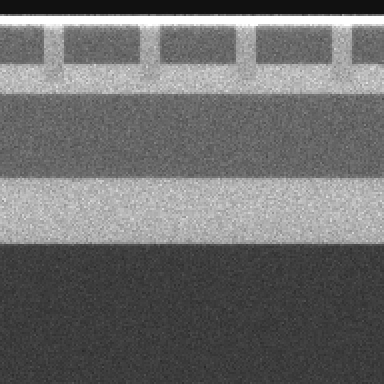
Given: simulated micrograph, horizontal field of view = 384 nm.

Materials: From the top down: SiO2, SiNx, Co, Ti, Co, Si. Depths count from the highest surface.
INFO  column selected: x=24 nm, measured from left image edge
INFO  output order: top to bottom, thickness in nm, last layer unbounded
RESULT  SiO2 8, SiNx 40, Co 30, Ti 84, Co 66, Si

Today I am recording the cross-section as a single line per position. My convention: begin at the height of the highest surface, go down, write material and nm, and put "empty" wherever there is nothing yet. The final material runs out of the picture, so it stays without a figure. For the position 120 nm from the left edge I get SiO2 8, SiNx 40, Co 30, Ti 84, Co 66, Si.